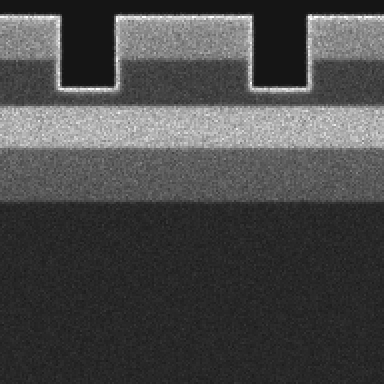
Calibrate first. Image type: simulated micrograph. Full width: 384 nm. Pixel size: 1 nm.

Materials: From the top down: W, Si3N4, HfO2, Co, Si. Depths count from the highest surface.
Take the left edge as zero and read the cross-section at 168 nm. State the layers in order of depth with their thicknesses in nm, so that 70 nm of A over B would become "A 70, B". W 44, Si3N4 46, HfO2 42, Co 54, Si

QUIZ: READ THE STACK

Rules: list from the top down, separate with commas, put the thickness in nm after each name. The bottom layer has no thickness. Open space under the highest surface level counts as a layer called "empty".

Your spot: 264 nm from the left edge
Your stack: empty 72, Si3N4 18, HfO2 42, Co 54, Si